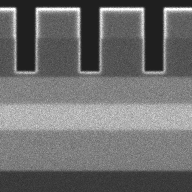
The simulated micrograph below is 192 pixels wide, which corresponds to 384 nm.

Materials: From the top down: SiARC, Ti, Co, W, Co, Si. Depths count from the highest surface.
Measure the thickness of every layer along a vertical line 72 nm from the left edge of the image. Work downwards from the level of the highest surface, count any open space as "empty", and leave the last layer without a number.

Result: SiARC 60, Ti 78, Co 54, W 52, Co 82, Si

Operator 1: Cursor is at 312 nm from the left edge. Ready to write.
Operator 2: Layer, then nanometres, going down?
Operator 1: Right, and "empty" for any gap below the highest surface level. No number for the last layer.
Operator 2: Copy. empty 128, Ti 10, Co 54, W 52, Co 82, Si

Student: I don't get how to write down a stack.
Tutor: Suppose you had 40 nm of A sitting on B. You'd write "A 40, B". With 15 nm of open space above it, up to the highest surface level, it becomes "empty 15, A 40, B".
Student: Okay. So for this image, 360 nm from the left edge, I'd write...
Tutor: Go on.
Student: SiARC 60, Ti 78, Co 54, W 52, Co 82, Si